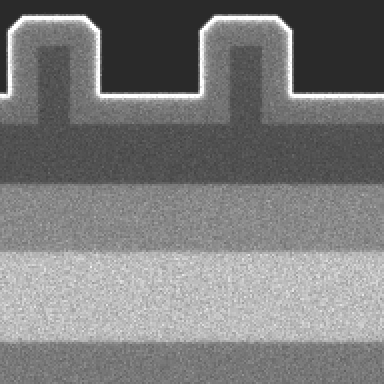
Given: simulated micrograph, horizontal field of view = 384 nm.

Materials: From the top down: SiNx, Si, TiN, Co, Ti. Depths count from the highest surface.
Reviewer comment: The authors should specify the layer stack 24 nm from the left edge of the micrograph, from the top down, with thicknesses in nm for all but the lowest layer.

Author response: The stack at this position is SiNx 108, Si 60, TiN 68, Co 90, Ti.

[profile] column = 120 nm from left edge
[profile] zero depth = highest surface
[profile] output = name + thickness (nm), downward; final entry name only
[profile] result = empty 78, SiNx 30, Si 60, TiN 68, Co 90, Ti